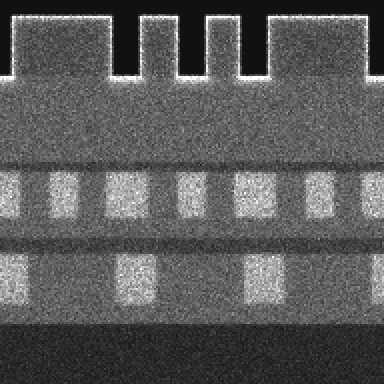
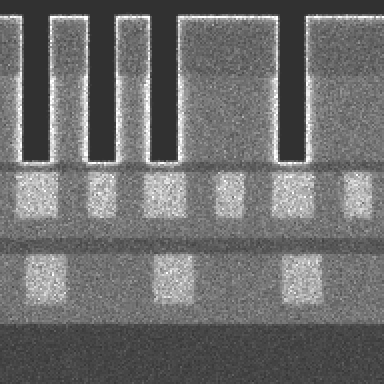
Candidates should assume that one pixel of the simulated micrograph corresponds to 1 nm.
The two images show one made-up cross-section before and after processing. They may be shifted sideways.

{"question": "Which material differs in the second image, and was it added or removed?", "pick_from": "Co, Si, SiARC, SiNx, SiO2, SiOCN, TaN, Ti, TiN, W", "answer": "SiO2, removed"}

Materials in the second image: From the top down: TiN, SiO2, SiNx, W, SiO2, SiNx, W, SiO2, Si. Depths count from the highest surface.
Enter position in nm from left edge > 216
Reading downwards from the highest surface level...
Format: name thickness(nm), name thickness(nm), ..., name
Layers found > TiN 60, SiO2 86, SiNx 10, W 46, SiO2 20, SiNx 16, SiO2 70, Si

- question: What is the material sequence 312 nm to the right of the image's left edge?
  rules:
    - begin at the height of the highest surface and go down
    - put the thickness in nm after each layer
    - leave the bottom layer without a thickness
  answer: TiN 60, SiO2 86, SiNx 10, W 46, SiO2 20, SiNx 16, W 50, SiO2 20, Si